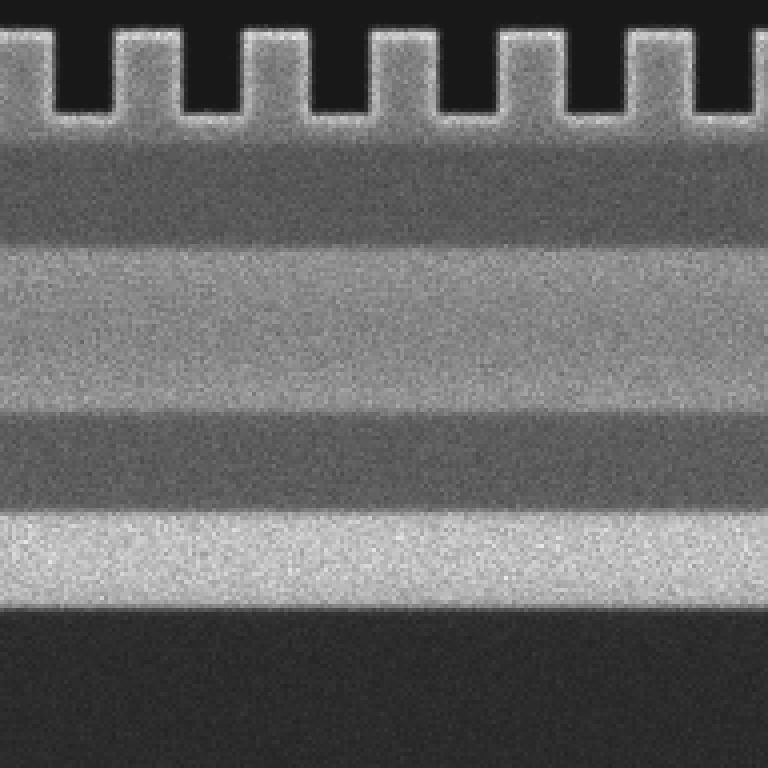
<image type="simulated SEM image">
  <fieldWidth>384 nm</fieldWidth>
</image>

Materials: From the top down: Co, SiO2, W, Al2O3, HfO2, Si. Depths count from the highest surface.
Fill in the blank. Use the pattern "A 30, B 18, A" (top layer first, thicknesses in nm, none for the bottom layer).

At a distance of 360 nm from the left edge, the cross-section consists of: empty 42, Co 14, SiO2 52, W 82, Al2O3 50, HfO2 48, Si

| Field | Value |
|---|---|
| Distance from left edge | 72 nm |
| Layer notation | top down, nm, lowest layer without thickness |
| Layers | Co 56, SiO2 52, W 82, Al2O3 50, HfO2 48, Si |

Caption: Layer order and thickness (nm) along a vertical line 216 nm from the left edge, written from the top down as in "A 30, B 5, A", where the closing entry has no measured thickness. Co 56, SiO2 52, W 82, Al2O3 50, HfO2 48, Si